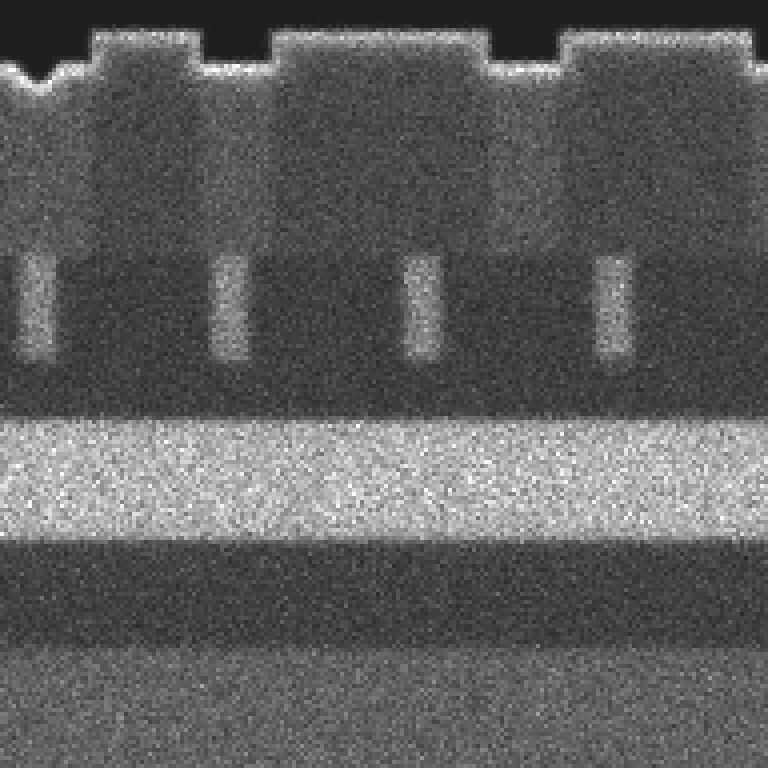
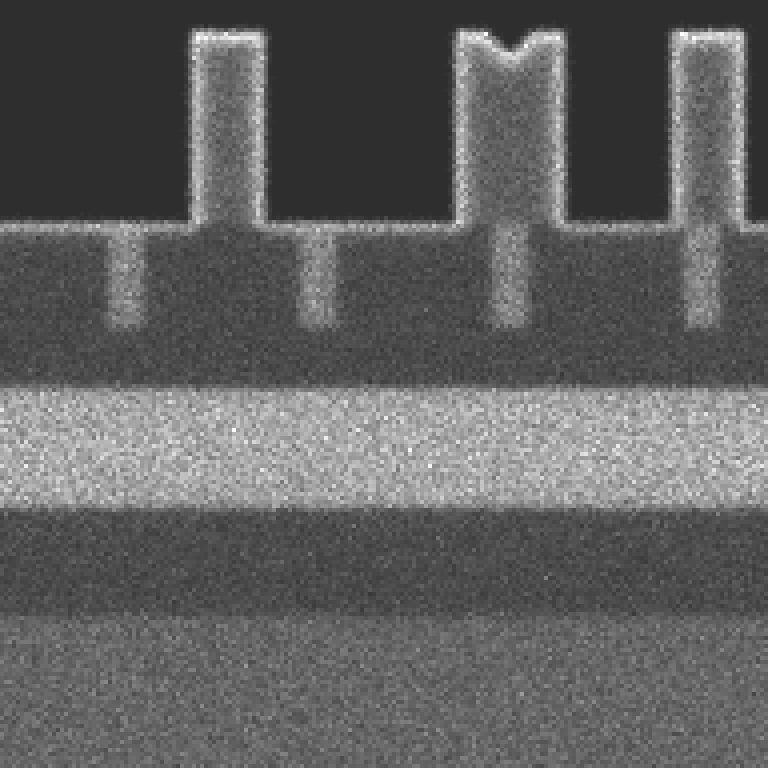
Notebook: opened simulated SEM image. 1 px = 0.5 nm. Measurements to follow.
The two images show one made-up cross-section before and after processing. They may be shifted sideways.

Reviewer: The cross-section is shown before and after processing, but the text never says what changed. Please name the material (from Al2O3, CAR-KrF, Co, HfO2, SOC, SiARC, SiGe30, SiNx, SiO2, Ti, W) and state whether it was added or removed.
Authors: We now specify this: SOC, removed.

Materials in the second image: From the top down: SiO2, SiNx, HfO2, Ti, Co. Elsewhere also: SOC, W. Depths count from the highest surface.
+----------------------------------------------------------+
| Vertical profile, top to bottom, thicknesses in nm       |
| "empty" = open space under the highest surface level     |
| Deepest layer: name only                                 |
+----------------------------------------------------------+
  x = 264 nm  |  empty 2, SiO2 94, SiNx 82, HfO2 60, Ti 54, Co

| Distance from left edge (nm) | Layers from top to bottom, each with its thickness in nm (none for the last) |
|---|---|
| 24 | empty 96, SiNx 82, HfO2 60, Ti 54, Co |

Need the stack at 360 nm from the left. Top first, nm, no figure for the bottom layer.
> SiO2 96, SiNx 82, HfO2 60, Ti 54, Co